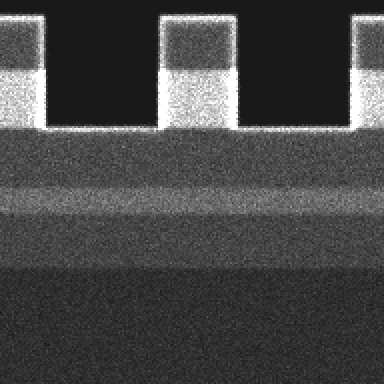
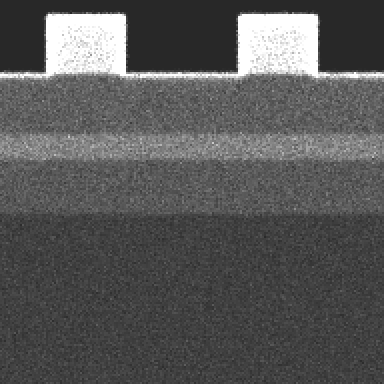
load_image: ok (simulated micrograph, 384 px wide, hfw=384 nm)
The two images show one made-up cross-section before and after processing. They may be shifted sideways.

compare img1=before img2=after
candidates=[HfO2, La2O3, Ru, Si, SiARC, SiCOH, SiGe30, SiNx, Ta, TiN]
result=removed:SiARC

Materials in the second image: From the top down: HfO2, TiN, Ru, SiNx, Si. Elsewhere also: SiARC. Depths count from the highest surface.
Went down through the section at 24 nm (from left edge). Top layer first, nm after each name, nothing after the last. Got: empty 58, TiN 60, Ru 26, SiNx 54, Si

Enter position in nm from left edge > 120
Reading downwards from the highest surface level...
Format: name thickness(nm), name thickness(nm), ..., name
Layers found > HfO2 58, TiN 60, Ru 26, SiNx 54, Si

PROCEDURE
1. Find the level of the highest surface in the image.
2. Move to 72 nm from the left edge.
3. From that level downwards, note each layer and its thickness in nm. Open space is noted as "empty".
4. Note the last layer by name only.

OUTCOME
HfO2 58, TiN 60, Ru 26, SiNx 54, Si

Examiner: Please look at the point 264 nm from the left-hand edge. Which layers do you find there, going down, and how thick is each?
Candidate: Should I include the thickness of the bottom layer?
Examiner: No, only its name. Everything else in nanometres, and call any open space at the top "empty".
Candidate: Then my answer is HfO2 58, TiN 60, Ru 26, SiNx 54, Si